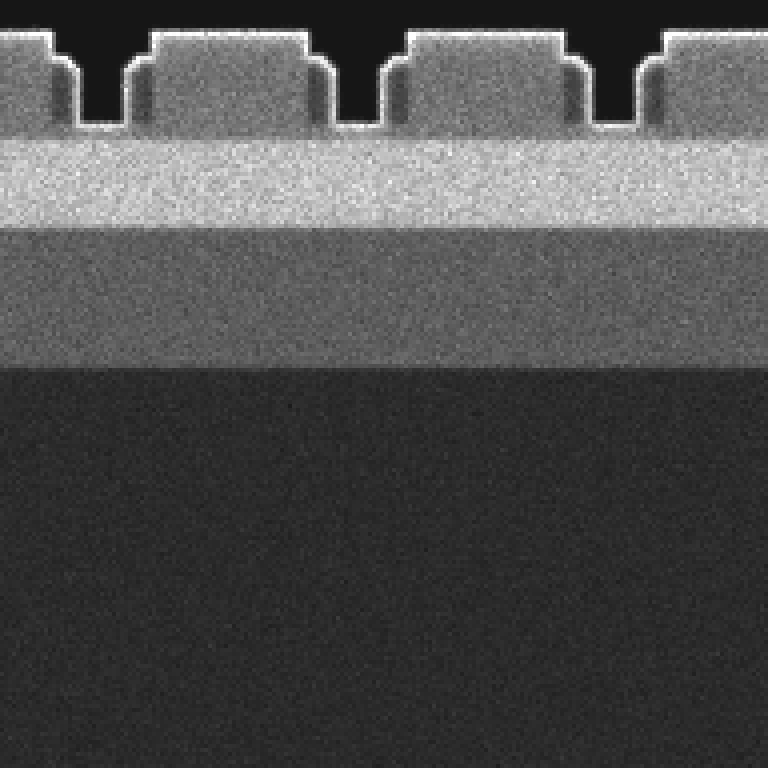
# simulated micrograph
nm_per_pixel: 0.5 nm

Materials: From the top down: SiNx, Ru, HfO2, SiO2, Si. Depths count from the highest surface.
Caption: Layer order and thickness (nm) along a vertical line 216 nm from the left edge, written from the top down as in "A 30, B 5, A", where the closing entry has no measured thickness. Ru 54, HfO2 44, SiO2 70, Si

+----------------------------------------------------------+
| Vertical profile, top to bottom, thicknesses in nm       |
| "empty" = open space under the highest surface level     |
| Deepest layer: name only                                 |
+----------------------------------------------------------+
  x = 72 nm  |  empty 12, SiNx 34, Ru 8, HfO2 44, SiO2 70, Si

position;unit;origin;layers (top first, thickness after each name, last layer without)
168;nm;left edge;empty 46, Ru 8, HfO2 44, SiO2 70, Si